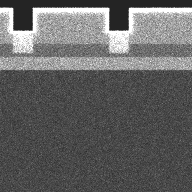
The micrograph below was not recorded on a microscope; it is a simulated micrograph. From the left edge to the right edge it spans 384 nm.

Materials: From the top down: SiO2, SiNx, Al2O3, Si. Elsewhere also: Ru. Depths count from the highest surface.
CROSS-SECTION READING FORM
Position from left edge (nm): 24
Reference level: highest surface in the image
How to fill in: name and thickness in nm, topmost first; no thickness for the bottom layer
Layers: SiO2 72, SiNx 26, Al2O3 26, Si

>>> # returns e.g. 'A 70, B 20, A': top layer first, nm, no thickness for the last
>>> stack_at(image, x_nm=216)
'SiO2 72, SiNx 26, Al2O3 26, Si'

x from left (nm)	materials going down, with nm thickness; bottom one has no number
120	SiO2 72, SiNx 26, Al2O3 26, Si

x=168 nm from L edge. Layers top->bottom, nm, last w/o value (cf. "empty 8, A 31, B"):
SiO2 72, SiNx 26, Al2O3 26, Si